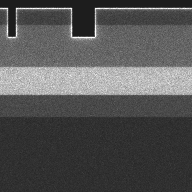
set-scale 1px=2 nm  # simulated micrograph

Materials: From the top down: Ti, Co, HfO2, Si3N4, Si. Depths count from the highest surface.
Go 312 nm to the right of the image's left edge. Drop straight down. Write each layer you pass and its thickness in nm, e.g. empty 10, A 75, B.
Ti 34, Co 84, HfO2 56, Si3N4 44, Si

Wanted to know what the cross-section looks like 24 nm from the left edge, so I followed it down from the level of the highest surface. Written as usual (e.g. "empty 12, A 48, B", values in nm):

empty 58, Co 60, HfO2 56, Si3N4 44, Si